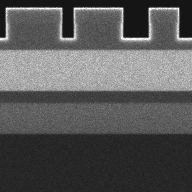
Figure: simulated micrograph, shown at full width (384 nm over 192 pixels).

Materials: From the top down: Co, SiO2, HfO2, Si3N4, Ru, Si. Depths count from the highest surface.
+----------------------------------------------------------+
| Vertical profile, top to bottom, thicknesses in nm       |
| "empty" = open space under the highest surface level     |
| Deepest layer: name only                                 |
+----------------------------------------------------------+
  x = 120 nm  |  Co 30, SiO2 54, HfO2 82, Si3N4 24, Ru 62, Si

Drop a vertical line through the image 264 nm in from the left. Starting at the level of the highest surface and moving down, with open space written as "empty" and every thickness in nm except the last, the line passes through empty 60, SiO2 24, HfO2 82, Si3N4 24, Ru 62, Si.